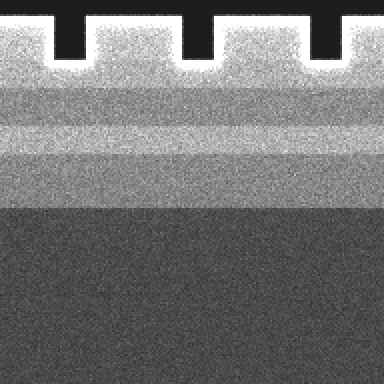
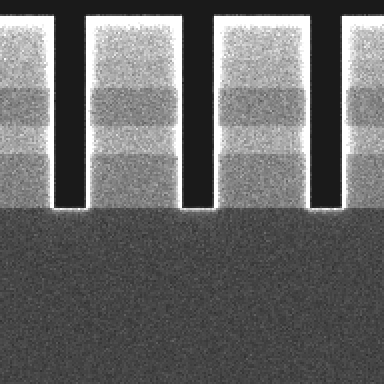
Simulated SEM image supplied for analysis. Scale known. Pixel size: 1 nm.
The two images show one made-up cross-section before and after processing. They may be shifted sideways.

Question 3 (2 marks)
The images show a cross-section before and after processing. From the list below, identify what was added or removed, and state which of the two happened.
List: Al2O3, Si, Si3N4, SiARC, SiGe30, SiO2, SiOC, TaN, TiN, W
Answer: Si3N4 and SiO2 was removed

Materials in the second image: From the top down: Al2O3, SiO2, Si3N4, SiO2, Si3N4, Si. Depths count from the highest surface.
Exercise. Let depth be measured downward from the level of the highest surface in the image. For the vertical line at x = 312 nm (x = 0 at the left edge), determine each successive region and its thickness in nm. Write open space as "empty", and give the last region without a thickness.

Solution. empty 192, Si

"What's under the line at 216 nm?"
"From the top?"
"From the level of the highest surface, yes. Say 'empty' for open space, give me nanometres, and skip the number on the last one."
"Al2O3 44, SiO2 28, Si3N4 38, SiO2 28, Si3N4 54, Si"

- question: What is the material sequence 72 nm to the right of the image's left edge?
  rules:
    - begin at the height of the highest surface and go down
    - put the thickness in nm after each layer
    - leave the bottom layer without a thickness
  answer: empty 192, Si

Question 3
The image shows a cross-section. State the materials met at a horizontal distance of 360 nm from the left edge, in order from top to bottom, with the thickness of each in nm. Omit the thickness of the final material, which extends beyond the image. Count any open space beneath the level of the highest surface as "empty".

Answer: Al2O3 44, SiO2 28, Si3N4 38, SiO2 28, Si3N4 54, Si